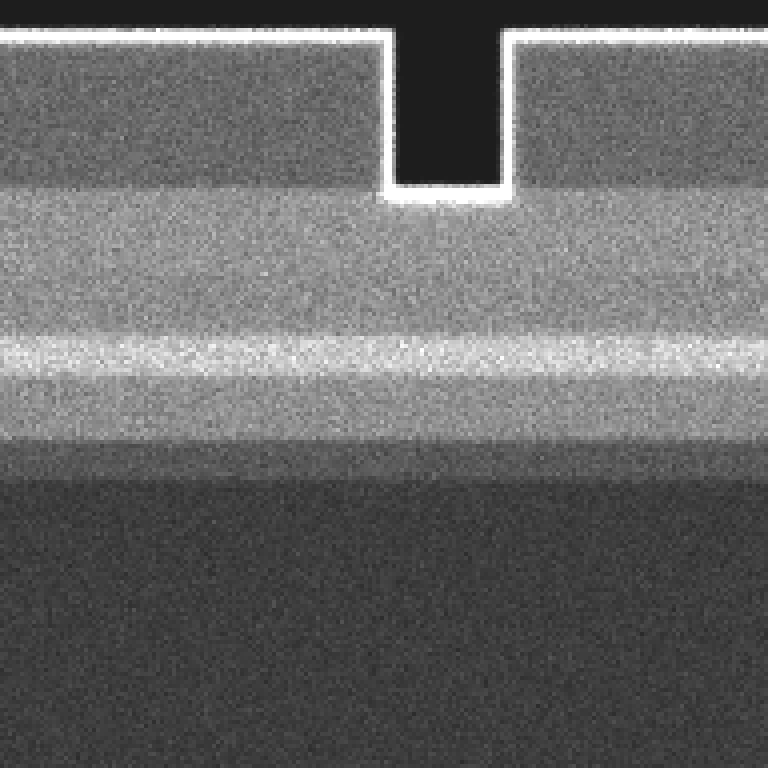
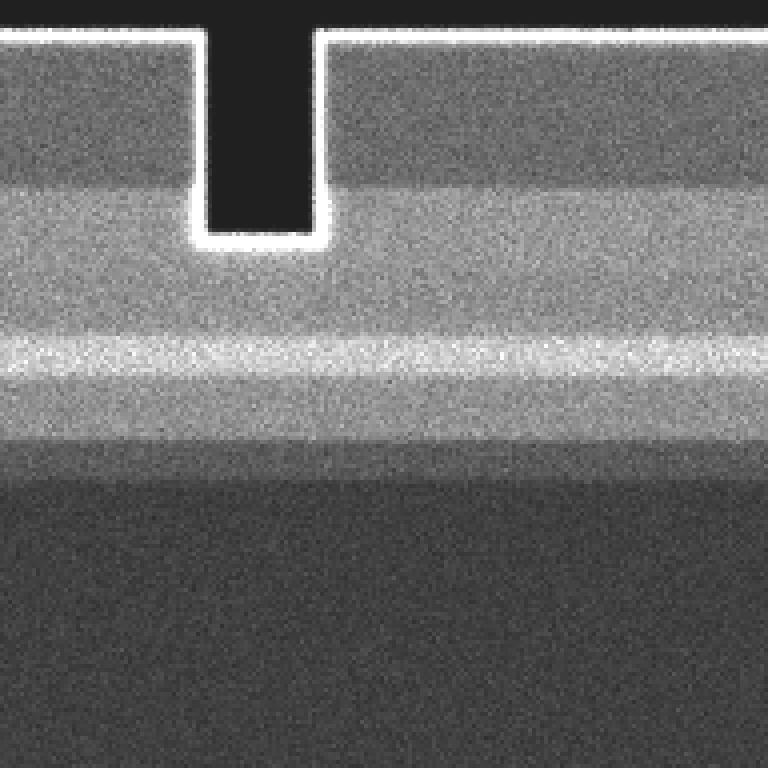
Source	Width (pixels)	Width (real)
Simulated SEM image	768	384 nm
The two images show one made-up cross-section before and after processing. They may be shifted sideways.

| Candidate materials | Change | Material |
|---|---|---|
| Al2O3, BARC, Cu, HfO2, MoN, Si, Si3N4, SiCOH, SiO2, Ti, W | removed | Al2O3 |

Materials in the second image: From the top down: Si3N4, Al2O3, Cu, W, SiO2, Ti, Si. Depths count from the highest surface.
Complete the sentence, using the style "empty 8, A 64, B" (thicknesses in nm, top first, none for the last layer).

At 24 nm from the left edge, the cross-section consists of Si3N4 78, Al2O3 42, Cu 32, W 20, SiO2 32, Ti 20, Si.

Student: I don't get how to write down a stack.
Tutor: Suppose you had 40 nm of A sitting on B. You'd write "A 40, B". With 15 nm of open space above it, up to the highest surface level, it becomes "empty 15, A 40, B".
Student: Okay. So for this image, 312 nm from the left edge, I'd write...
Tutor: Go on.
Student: Si3N4 78, Al2O3 42, Cu 32, W 20, SiO2 32, Ti 20, Si